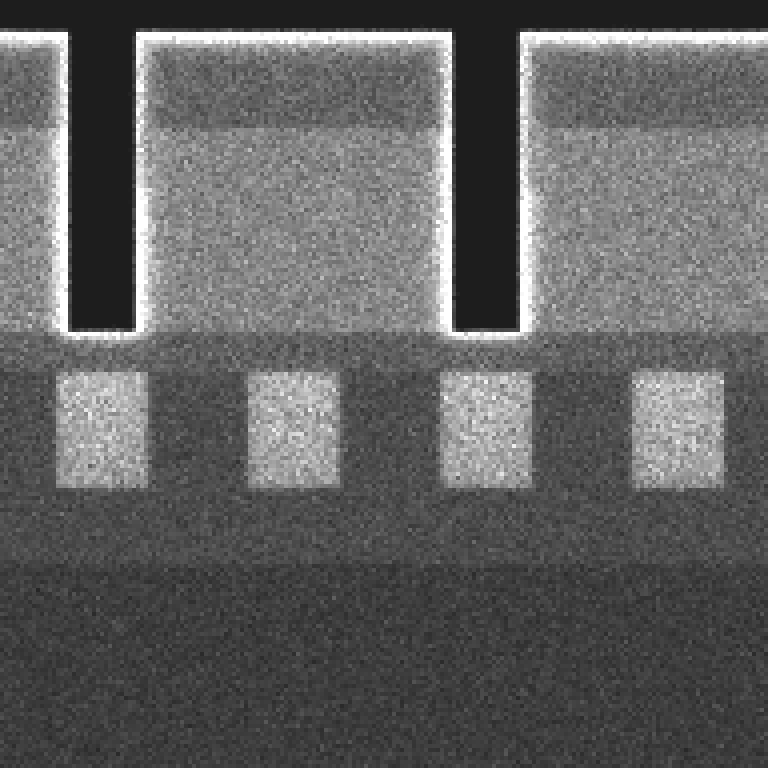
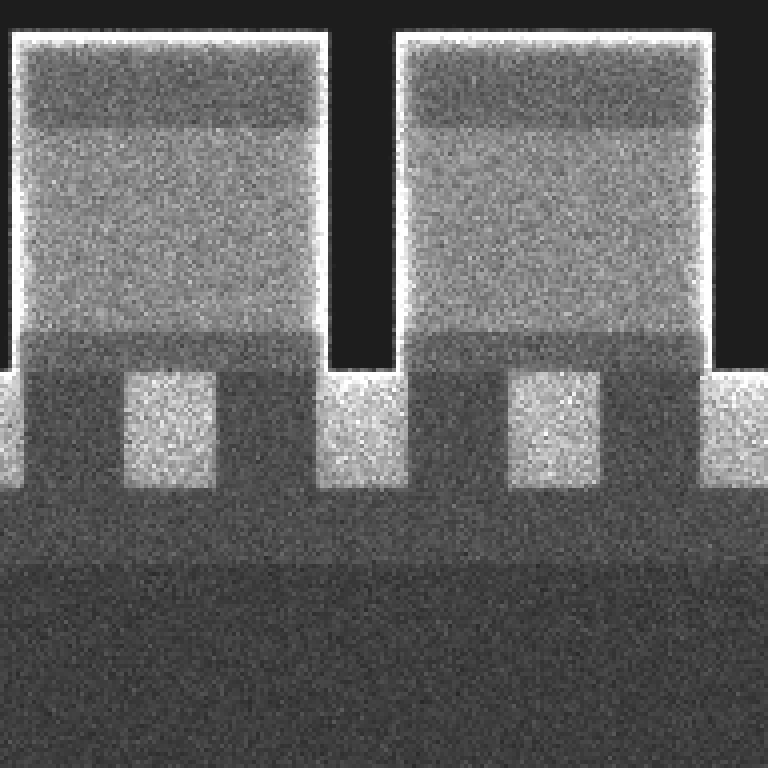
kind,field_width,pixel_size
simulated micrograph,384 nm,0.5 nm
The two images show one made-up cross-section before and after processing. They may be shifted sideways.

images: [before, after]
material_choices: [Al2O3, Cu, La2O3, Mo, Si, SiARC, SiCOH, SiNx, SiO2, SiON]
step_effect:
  removed: SiNx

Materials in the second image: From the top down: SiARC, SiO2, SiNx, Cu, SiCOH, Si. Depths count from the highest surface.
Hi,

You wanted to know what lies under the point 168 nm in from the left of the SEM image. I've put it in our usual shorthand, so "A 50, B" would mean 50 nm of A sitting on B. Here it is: empty 170, Cu 58, SiCOH 38, Si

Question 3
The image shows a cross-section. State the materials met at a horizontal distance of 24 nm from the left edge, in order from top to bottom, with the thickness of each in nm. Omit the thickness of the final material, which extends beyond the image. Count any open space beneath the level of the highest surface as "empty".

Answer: SiARC 48, SiO2 102, SiNx 20, SiCOH 96, Si